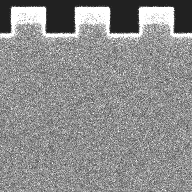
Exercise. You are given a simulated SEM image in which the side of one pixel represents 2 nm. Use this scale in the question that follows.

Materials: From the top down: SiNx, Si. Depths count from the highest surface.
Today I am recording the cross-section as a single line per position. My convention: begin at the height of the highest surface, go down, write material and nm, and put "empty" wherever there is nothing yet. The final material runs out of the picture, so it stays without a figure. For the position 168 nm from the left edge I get SiNx 32, Si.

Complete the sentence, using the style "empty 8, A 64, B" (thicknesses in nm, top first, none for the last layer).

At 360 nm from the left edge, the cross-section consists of empty 52, Si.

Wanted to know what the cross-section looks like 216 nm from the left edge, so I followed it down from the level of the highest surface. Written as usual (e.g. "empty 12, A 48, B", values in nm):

SiNx 32, Si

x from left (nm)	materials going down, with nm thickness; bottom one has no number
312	SiNx 32, Si